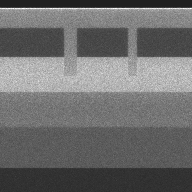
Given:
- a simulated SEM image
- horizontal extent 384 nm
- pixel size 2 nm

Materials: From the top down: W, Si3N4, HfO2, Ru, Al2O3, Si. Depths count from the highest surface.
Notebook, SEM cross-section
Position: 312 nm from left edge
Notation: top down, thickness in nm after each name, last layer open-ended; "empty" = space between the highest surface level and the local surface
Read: W 40, Si3N4 58, HfO2 70, Ru 70, Al2O3 82, Si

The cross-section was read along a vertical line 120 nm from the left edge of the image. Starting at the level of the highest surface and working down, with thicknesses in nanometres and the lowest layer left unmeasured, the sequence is W 40, Si3N4 58, HfO2 70, Ru 70, Al2O3 82, Si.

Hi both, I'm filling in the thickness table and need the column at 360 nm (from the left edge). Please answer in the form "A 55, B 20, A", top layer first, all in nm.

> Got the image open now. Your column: W 40, Si3N4 58, HfO2 70, Ru 70, Al2O3 82, Si